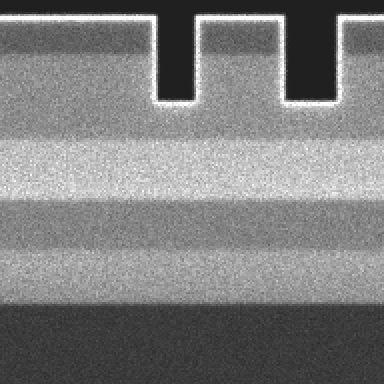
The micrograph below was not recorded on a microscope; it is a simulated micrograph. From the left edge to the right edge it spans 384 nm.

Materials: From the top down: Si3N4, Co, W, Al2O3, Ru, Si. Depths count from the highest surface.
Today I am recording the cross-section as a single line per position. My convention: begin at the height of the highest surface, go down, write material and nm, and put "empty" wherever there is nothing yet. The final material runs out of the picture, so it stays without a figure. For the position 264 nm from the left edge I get Si3N4 38, Co 86, W 60, Al2O3 50, Ru 54, Si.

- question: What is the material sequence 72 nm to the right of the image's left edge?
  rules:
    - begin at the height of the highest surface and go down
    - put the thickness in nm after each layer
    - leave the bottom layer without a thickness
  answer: Si3N4 38, Co 86, W 60, Al2O3 50, Ru 54, Si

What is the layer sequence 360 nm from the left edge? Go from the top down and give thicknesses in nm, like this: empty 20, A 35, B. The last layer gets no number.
Si3N4 38, Co 86, W 60, Al2O3 50, Ru 54, Si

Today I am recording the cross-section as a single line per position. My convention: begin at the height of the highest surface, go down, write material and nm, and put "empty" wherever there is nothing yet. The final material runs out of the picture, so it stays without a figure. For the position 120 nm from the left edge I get Si3N4 38, Co 86, W 60, Al2O3 50, Ru 54, Si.